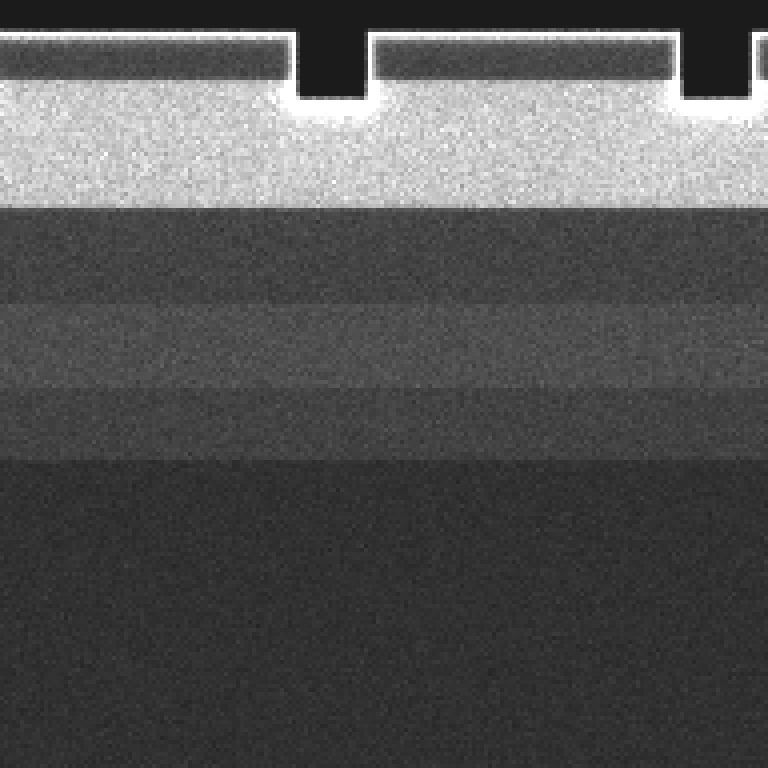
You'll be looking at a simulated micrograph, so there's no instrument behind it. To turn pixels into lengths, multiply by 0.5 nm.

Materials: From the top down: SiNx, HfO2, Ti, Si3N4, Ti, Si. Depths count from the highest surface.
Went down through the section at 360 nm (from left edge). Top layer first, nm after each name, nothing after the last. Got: empty 34, HfO2 54, Ti 48, Si3N4 42, Ti 36, Si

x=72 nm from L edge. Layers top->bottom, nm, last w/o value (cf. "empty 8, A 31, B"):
SiNx 24, HfO2 64, Ti 48, Si3N4 42, Ti 36, Si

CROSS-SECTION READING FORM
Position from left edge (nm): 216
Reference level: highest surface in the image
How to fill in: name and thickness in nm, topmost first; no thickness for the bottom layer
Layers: SiNx 24, HfO2 64, Ti 48, Si3N4 42, Ti 36, Si